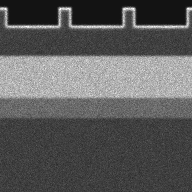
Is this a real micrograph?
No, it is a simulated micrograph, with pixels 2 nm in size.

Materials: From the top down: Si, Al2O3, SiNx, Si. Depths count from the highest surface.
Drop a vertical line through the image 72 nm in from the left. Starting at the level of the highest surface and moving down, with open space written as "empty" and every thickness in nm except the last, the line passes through empty 36, Si 60, Al2O3 84, SiNx 40, Si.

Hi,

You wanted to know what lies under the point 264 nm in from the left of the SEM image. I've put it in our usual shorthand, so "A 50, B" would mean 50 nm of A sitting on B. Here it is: Si 96, Al2O3 84, SiNx 40, Si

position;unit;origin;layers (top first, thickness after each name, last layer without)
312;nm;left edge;empty 36, Si 60, Al2O3 84, SiNx 40, Si